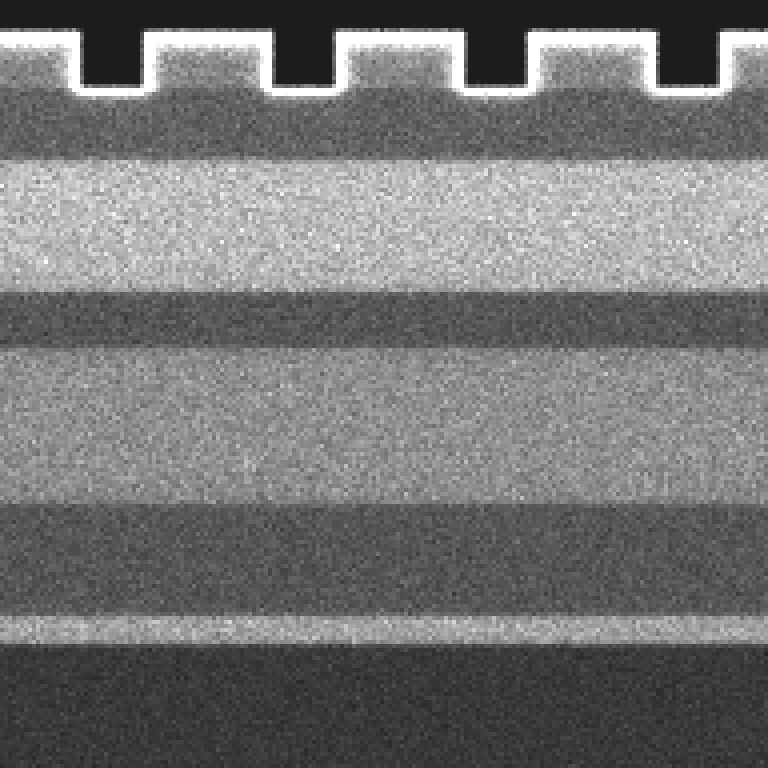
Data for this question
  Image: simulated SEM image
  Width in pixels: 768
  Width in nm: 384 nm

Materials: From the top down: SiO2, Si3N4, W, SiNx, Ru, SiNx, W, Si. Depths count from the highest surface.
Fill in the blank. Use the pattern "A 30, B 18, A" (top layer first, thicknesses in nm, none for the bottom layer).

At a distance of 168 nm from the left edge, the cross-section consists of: SiO2 28, Si3N4 36, W 66, SiNx 28, Ru 78, SiNx 56, W 14, Si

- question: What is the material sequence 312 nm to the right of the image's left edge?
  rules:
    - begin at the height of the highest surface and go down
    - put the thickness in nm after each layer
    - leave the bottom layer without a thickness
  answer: SiO2 28, Si3N4 36, W 66, SiNx 28, Ru 78, SiNx 56, W 14, Si